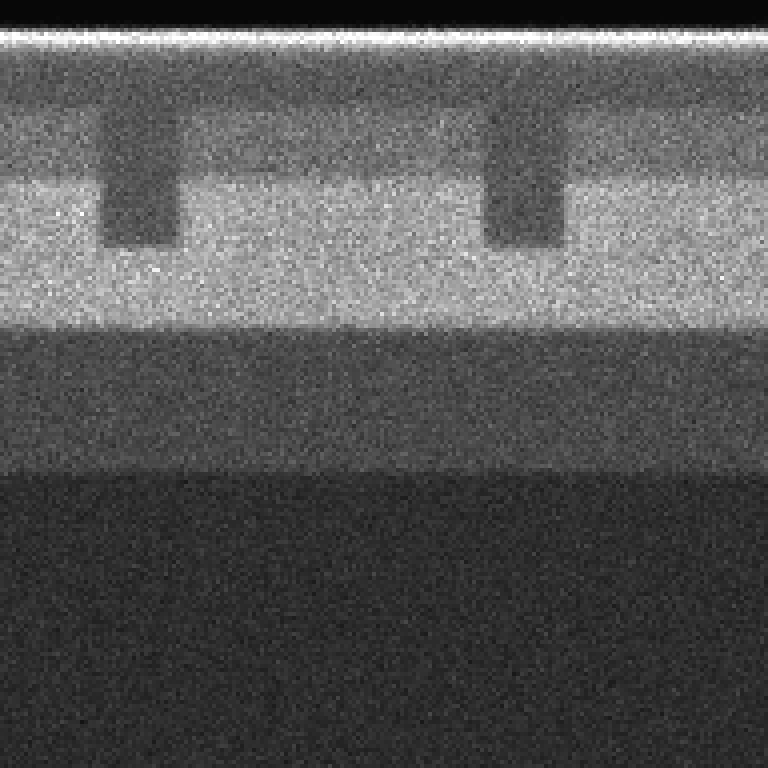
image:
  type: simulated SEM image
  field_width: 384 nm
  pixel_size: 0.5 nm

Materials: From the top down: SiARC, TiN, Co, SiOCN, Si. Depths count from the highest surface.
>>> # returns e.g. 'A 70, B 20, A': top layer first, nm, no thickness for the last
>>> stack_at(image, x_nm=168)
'SiARC 38, TiN 36, Co 74, SiOCN 72, Si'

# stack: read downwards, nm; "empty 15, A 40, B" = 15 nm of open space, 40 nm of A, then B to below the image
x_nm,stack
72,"SiARC 108, Co 40, SiOCN 72, Si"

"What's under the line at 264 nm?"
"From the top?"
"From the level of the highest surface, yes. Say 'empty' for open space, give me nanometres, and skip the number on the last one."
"SiARC 108, Co 40, SiOCN 72, Si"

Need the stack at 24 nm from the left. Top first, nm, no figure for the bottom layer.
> SiARC 38, TiN 36, Co 74, SiOCN 72, Si